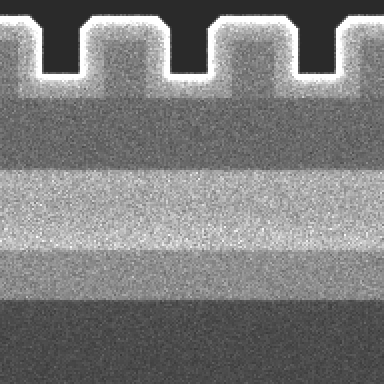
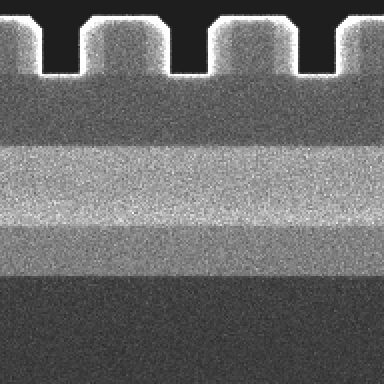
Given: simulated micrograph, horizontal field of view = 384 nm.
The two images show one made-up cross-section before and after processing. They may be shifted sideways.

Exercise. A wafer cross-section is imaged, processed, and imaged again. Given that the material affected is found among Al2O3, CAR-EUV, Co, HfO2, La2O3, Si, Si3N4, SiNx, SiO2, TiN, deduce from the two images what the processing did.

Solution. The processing removed Al2O3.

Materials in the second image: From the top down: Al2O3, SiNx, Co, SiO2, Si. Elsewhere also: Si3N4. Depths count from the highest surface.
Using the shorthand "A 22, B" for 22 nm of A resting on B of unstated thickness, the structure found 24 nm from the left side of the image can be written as Al2O3 58, SiNx 72, Co 80, SiO2 50, Si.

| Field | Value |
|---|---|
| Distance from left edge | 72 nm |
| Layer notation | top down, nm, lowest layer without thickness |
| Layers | empty 58, SiNx 72, Co 80, SiO2 50, Si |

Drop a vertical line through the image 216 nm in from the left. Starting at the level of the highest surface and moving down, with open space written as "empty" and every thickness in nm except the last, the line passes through empty 4, Al2O3 54, SiNx 72, Co 80, SiO2 50, Si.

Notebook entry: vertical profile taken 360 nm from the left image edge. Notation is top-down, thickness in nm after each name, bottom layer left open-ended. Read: Si3N4 58, SiNx 72, Co 80, SiO2 50, Si